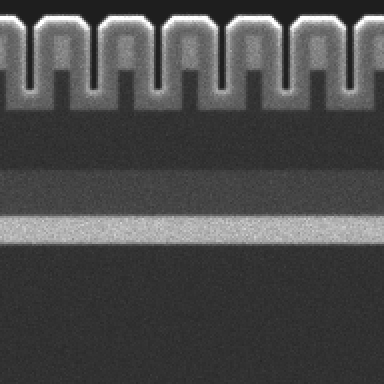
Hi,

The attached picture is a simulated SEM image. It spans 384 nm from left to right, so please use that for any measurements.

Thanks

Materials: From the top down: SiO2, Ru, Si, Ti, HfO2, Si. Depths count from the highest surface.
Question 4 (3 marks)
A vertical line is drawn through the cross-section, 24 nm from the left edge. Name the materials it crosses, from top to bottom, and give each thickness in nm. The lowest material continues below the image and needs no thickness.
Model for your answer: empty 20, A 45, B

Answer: empty 10, SiO2 84, Si 60, Ti 46, HfO2 28, Si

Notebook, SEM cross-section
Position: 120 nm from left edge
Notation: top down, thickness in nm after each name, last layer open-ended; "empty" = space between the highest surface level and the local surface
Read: SiO2 20, Ru 34, Si 100, Ti 46, HfO2 28, Si